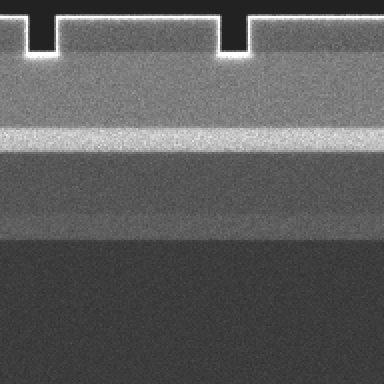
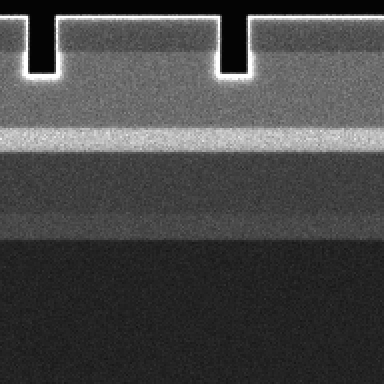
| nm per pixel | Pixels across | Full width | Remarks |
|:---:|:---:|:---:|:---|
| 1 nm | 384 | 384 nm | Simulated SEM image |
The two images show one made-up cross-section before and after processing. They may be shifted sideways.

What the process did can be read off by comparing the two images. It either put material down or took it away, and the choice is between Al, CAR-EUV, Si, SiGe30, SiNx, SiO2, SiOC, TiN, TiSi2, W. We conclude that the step removed SiO2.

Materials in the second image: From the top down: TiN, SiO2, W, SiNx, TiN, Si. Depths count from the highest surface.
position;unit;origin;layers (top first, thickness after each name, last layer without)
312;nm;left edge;TiN 36, SiO2 76, W 24, SiNx 62, TiN 26, Si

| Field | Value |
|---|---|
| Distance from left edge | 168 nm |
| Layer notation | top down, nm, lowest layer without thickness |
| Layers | TiN 36, SiO2 76, W 24, SiNx 62, TiN 26, Si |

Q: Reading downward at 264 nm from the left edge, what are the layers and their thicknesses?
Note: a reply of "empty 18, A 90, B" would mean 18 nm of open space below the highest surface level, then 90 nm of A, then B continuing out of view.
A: TiN 36, SiO2 76, W 24, SiNx 62, TiN 26, Si